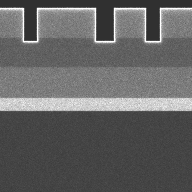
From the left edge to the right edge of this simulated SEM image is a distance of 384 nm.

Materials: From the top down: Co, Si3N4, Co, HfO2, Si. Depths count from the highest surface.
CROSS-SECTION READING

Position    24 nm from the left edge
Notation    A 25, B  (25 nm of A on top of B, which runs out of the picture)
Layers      Co 60, Si3N4 58, Co 62, HfO2 26, Si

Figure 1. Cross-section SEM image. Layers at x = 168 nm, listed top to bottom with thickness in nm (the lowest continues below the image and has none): Co 60, Si3N4 58, Co 62, HfO2 26, Si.